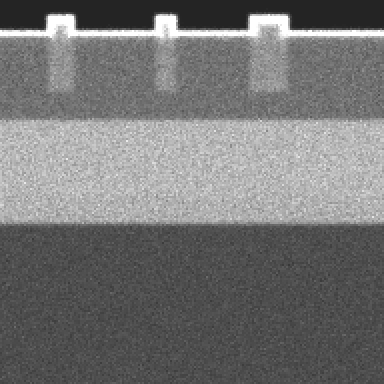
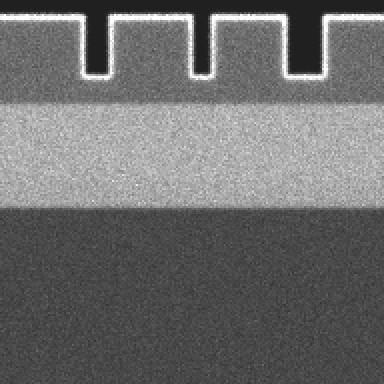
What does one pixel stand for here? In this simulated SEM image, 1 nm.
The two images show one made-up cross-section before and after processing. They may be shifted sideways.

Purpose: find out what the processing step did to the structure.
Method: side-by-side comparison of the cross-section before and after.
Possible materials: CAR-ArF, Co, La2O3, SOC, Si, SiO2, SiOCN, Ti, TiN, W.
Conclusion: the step removed SOC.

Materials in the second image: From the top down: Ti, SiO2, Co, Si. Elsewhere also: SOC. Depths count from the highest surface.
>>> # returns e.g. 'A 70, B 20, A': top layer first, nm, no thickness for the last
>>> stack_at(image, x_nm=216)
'Ti 88, SiO2 76, Co 28, Si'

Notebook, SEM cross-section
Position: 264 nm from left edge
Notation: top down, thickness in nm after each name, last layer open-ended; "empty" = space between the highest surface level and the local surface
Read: Ti 88, SiO2 76, Co 28, Si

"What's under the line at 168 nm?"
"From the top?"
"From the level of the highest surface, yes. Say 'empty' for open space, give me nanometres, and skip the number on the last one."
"Ti 88, SiO2 76, Co 28, Si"